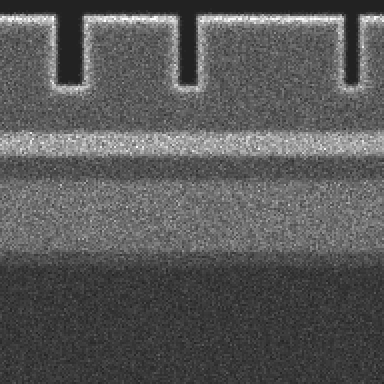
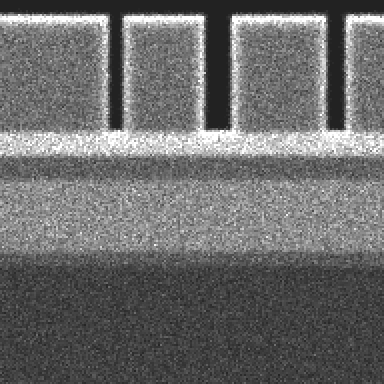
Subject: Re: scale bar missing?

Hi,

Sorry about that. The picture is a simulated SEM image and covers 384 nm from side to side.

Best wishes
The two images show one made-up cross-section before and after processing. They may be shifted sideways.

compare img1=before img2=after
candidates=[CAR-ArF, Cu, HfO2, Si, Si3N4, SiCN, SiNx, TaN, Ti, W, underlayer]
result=removed:underlayer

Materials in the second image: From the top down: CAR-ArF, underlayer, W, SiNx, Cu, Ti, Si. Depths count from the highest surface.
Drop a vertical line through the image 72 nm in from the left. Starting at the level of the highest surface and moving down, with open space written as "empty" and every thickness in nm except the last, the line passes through CAR-ArF 70, underlayer 46, W 24, SiNx 24, Cu 72, Ti 14, Si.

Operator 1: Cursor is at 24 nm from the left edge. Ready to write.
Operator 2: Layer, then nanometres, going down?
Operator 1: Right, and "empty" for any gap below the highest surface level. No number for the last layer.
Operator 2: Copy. CAR-ArF 70, underlayer 46, W 24, SiNx 24, Cu 72, Ti 14, Si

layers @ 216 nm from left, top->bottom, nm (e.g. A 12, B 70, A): empty 116, W 24, SiNx 24, Cu 72, Ti 14, Si